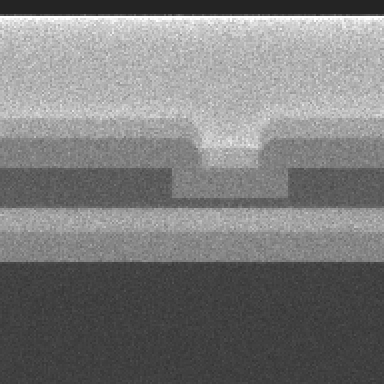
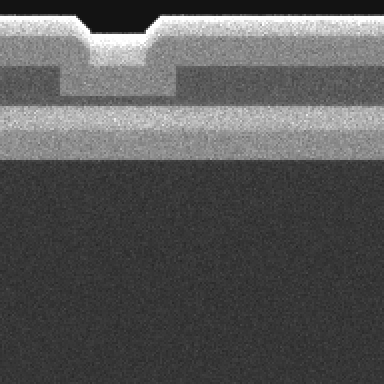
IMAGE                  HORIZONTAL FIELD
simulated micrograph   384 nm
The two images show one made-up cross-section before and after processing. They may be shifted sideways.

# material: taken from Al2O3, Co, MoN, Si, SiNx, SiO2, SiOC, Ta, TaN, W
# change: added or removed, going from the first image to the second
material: W
change: removed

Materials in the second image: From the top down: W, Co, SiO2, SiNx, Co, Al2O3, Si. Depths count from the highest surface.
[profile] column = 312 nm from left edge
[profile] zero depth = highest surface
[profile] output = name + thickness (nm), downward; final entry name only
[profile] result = Co 20, SiO2 30, SiNx 40, Co 24, Al2O3 30, Si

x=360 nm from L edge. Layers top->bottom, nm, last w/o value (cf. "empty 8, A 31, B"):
Co 20, SiO2 30, SiNx 40, Co 24, Al2O3 30, Si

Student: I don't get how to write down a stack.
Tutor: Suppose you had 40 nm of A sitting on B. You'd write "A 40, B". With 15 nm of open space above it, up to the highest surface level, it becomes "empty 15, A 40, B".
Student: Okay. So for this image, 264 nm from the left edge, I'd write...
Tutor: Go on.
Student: Co 20, SiO2 30, SiNx 40, Co 24, Al2O3 30, Si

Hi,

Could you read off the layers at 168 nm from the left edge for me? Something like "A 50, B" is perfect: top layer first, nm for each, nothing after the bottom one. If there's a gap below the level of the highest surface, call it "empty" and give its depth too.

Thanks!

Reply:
Co 20, SiO2 60, SiNx 10, Co 24, Al2O3 30, Si